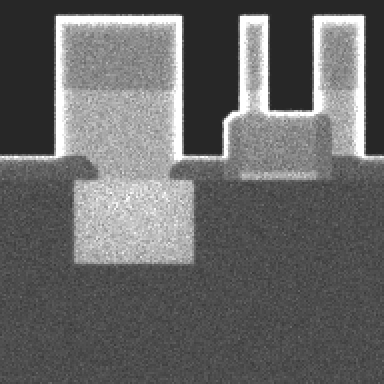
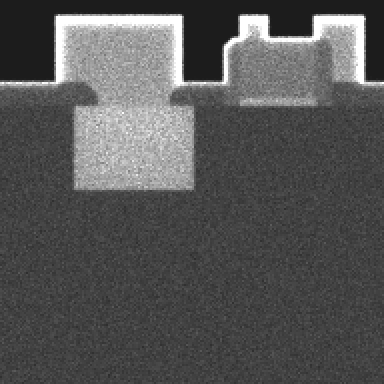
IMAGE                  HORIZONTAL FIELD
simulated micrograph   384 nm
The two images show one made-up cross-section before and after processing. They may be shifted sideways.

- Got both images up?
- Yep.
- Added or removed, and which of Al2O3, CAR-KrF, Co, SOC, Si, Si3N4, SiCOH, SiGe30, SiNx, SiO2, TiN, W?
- removed, SOC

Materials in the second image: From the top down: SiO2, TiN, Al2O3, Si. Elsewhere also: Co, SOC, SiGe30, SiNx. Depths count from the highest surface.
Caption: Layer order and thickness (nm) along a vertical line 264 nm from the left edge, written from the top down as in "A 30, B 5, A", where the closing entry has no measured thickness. SiO2 22, TiN 60, Al2O3 8, Si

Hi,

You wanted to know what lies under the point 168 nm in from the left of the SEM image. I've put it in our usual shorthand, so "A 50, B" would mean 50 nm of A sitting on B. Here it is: SiO2 90, Co 84, Si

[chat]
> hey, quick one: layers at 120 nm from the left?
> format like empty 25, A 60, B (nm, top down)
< SiO2 90, Co 84, Si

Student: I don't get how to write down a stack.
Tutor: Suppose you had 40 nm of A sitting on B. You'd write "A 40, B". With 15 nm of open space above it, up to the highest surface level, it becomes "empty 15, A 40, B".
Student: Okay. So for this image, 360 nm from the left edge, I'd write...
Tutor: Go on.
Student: SiO2 66, SiGe30 24, Si